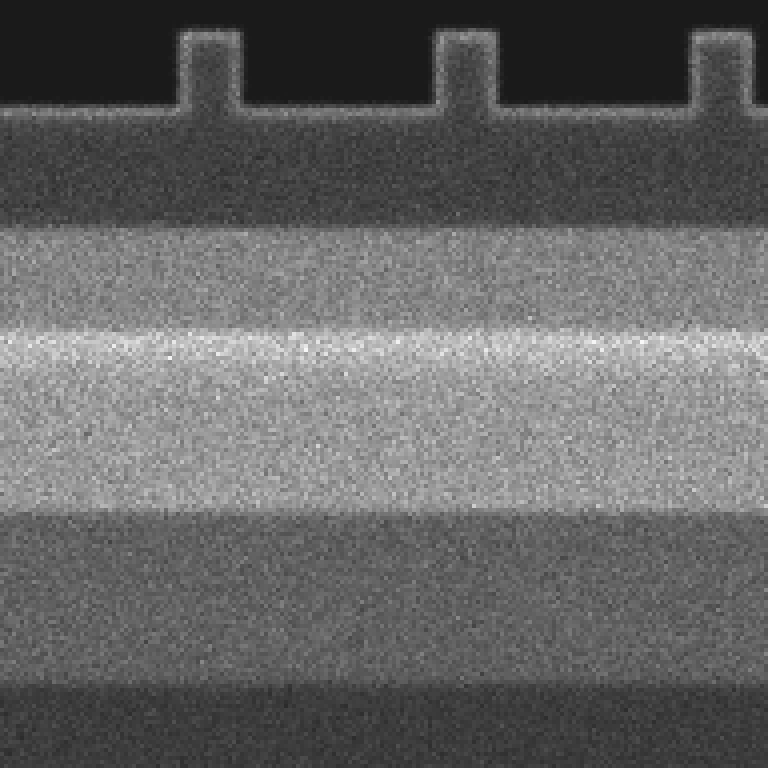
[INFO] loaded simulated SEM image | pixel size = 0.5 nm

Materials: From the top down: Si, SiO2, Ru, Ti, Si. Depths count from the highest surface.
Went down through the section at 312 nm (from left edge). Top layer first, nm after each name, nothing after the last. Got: empty 38, Si 60, SiO2 52, Ru 90, Ti 86, Si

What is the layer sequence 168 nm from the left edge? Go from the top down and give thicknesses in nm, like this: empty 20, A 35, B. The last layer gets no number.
empty 38, Si 60, SiO2 52, Ru 90, Ti 86, Si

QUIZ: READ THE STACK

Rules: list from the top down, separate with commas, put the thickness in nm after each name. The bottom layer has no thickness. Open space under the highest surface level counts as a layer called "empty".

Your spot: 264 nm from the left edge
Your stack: empty 38, Si 60, SiO2 52, Ru 90, Ti 86, Si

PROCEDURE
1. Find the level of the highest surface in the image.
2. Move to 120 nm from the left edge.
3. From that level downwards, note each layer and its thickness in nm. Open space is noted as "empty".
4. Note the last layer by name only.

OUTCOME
empty 38, Si 60, SiO2 52, Ru 90, Ti 86, Si